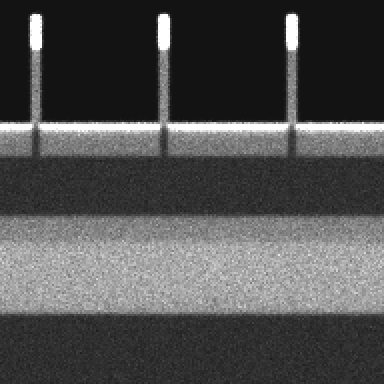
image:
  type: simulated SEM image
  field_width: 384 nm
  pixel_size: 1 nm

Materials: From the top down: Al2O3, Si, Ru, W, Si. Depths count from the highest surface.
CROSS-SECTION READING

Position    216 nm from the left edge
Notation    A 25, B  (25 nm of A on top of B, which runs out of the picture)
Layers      empty 108, Al2O3 32, Si 60, Ru 26, W 72, Si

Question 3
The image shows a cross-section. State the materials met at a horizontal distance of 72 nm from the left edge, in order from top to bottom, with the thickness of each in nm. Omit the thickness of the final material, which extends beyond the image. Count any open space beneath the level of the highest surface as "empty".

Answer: empty 108, Al2O3 32, Si 60, Ru 26, W 72, Si